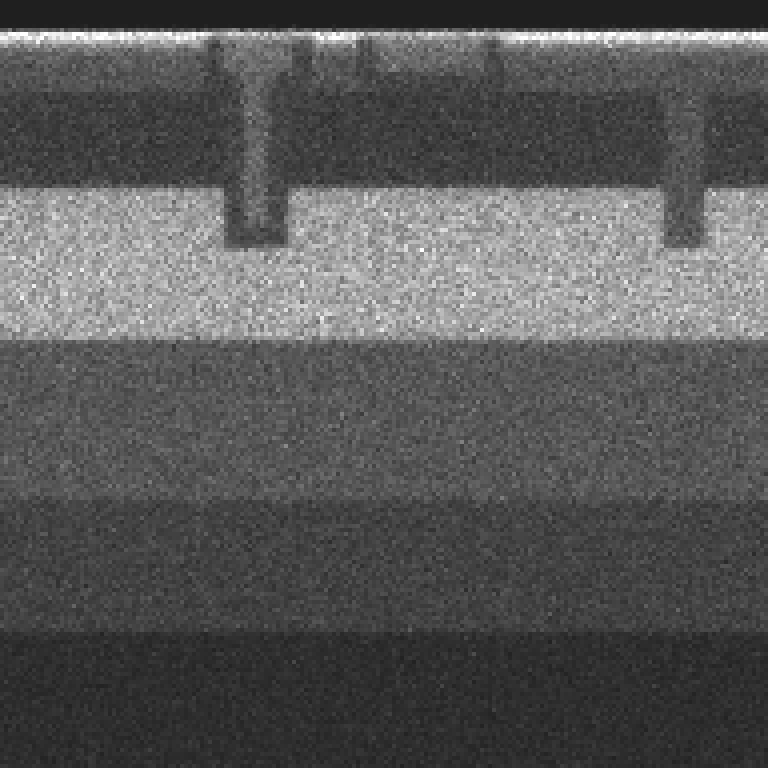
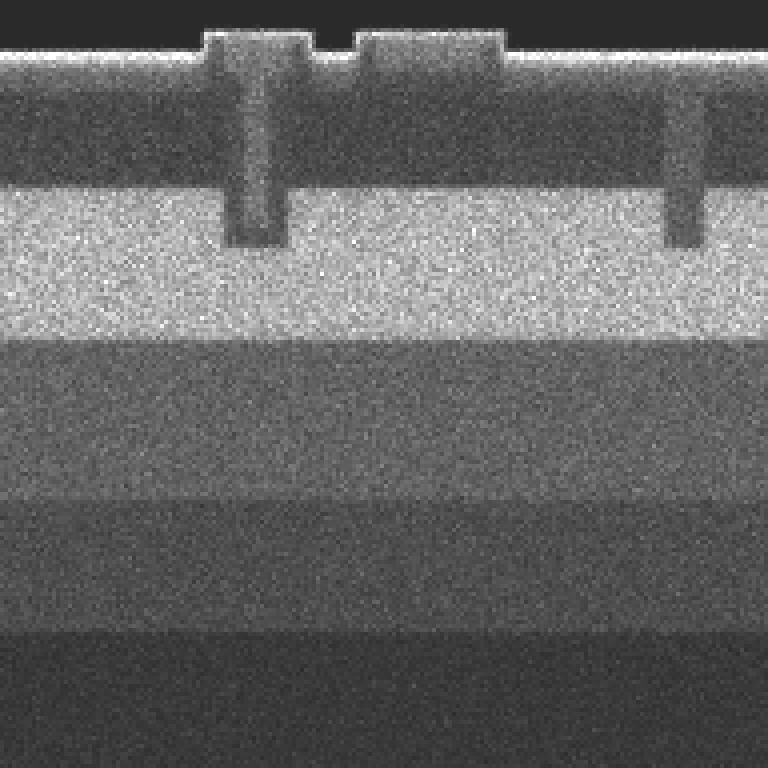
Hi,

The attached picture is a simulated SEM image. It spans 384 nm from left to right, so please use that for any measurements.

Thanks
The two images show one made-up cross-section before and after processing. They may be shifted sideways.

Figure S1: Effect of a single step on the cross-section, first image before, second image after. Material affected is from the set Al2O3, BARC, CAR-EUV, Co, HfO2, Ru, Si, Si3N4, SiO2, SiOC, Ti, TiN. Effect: removed SiO2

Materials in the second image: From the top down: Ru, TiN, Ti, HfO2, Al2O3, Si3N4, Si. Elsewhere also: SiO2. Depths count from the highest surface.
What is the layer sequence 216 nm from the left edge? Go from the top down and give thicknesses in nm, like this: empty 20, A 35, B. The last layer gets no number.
Ru 20, TiN 10, Ti 48, HfO2 76, Al2O3 80, Si3N4 66, Si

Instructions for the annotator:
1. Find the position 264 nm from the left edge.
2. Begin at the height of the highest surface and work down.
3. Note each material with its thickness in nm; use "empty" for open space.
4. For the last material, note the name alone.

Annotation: empty 10, SiO2 20, Ti 48, HfO2 76, Al2O3 80, Si3N4 66, Si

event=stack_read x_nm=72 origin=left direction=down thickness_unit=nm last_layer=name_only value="empty 10, SiO2 20, Ti 48, HfO2 76, Al2O3 80, Si3N4 66, Si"